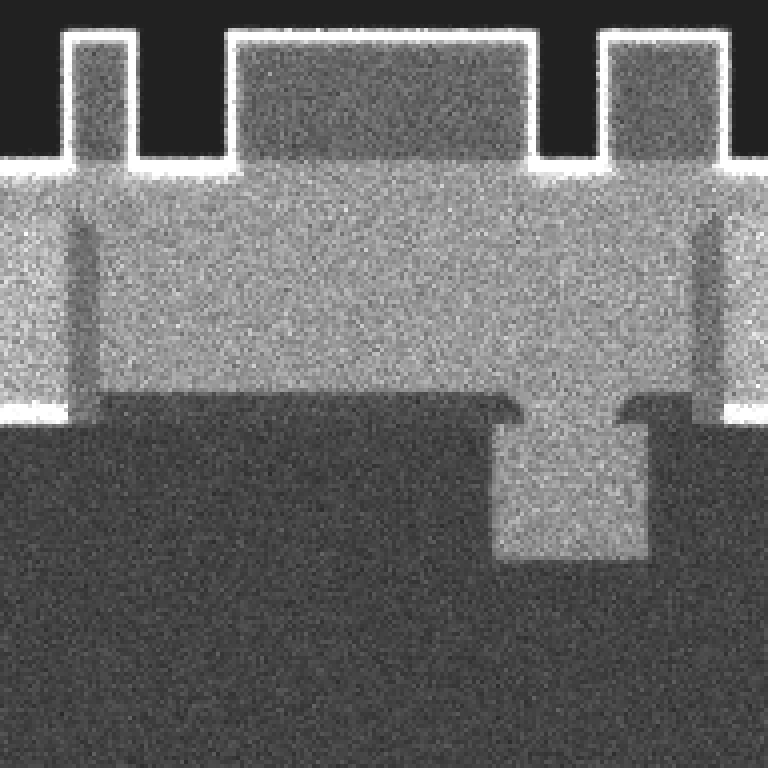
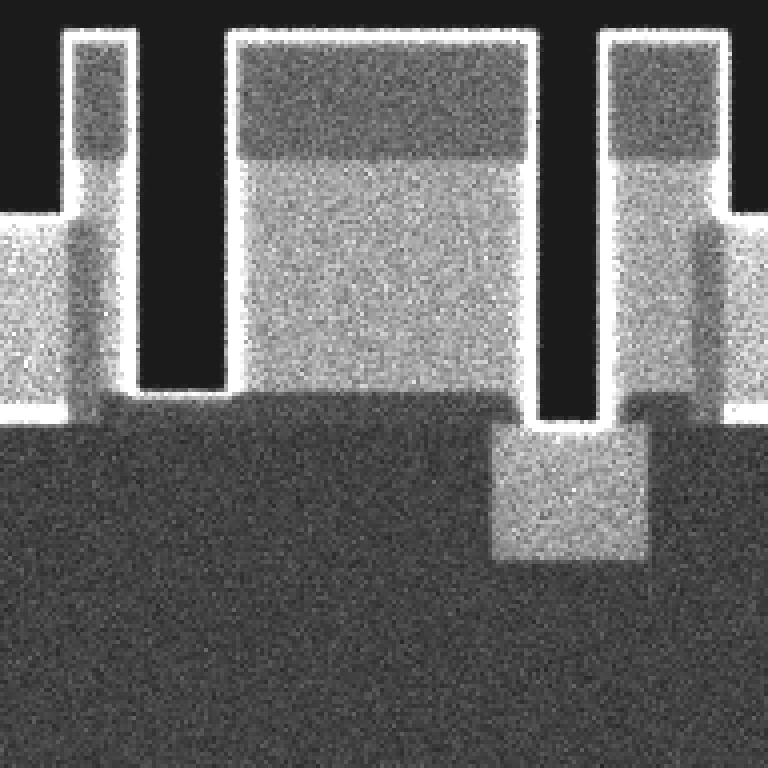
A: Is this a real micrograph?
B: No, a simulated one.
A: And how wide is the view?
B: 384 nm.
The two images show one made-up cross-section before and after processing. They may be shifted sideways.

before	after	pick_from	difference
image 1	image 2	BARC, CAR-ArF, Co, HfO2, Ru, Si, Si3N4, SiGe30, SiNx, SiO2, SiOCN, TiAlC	SiO2 removed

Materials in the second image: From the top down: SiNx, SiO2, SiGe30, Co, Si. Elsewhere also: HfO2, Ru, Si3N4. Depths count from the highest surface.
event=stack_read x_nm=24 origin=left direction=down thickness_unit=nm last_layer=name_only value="empty 92, Ru 94, HfO2 10, Si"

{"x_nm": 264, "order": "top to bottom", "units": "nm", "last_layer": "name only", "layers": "SiNx 64, SiO2 132, Co 68, Si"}